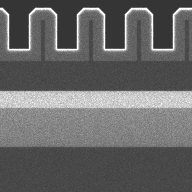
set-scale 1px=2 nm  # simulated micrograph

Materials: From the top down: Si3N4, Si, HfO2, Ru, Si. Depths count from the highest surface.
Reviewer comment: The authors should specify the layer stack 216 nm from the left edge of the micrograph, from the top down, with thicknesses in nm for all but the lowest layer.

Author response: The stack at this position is empty 82, Si3N4 24, Si 60, HfO2 34, Ru 78, Si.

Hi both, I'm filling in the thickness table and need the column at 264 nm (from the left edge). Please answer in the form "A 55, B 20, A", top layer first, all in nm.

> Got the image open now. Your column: Si3N4 106, Si 60, HfO2 34, Ru 78, Si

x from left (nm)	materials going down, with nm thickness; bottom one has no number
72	Si3N4 106, Si 60, HfO2 34, Ru 78, Si